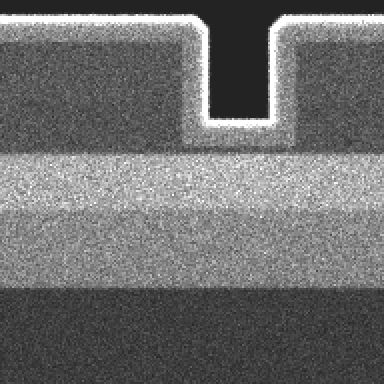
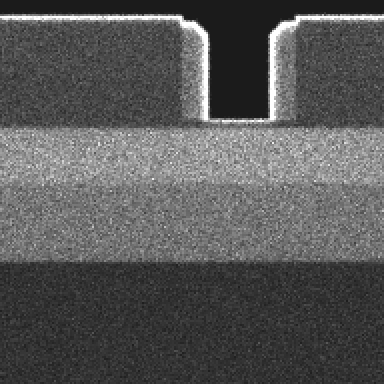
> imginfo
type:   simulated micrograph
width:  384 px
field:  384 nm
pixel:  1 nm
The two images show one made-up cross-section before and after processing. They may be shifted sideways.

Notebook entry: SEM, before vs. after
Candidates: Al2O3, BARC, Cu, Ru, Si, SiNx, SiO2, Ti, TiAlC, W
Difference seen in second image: Al2O3 removed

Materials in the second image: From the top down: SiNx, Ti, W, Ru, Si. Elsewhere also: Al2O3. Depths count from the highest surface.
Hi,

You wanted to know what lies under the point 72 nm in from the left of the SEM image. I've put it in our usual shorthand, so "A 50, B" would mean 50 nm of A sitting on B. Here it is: SiNx 60, Ti 52, W 56, Ru 78, Si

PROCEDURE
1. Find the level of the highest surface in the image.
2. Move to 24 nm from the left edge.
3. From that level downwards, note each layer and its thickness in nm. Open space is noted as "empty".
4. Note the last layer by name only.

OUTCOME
SiNx 60, Ti 52, W 56, Ru 78, Si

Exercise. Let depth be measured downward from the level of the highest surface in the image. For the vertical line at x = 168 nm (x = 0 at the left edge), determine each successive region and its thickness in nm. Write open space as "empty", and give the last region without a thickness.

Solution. SiNx 60, Ti 52, W 56, Ru 78, Si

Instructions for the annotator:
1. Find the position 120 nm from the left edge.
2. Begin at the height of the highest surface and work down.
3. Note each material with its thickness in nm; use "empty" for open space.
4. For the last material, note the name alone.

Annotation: SiNx 60, Ti 52, W 56, Ru 78, Si